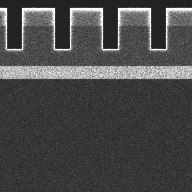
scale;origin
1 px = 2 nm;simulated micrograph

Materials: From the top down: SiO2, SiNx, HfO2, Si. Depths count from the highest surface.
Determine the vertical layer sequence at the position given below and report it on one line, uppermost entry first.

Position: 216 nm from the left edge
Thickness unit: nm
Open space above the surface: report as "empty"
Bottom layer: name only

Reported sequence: empty 82, SiNx 34, HfO2 26, Si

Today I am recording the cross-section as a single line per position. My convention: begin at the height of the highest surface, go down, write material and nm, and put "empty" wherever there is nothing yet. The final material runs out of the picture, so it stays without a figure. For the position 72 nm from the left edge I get SiO2 36, SiNx 80, HfO2 26, Si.